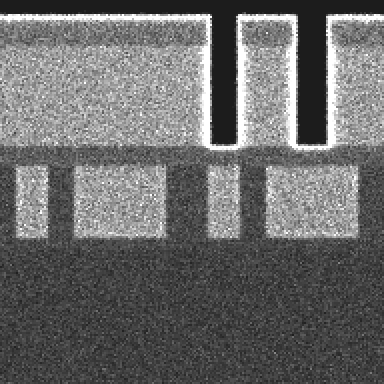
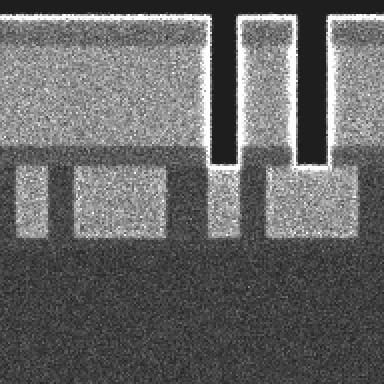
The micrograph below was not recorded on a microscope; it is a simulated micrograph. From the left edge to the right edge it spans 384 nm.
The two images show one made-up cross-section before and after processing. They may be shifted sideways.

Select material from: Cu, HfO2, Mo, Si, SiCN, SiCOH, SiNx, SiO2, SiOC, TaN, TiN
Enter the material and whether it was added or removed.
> SiCN / removed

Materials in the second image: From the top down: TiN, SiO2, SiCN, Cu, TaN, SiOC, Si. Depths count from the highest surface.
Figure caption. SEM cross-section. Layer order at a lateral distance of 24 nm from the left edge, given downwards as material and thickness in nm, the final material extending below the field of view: TiN 30, SiO2 100, SiCN 20, Cu 66, TaN 6, SiOC 12, Si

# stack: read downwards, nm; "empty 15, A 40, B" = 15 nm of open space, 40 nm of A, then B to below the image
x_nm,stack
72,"TiN 30, SiO2 100, SiCN 20, SiOC 84, Si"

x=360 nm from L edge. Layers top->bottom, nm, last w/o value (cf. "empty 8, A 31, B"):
TiN 30, SiO2 100, SiCN 20, SiOC 84, Si